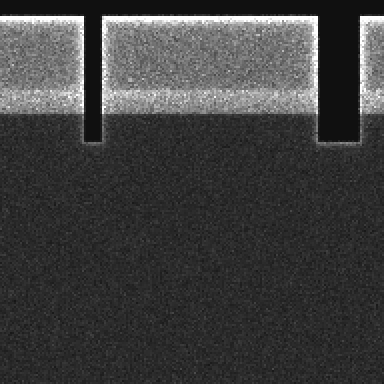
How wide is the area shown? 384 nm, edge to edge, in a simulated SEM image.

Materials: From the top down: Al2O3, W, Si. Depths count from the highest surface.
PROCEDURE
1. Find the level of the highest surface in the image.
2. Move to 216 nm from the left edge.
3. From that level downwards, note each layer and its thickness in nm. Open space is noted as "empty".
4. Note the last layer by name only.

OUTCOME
Al2O3 74, W 24, Si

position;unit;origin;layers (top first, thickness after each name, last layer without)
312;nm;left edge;Al2O3 74, W 24, Si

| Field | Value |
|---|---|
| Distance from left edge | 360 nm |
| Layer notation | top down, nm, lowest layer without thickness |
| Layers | Al2O3 74, W 24, Si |